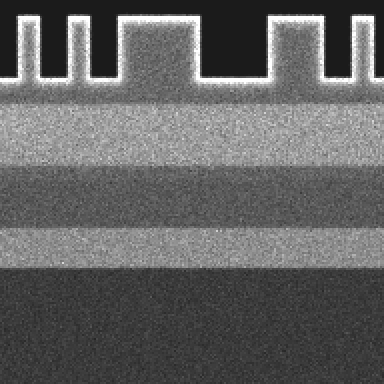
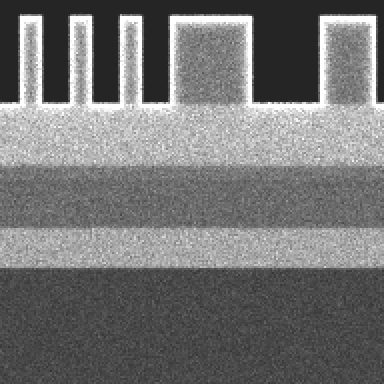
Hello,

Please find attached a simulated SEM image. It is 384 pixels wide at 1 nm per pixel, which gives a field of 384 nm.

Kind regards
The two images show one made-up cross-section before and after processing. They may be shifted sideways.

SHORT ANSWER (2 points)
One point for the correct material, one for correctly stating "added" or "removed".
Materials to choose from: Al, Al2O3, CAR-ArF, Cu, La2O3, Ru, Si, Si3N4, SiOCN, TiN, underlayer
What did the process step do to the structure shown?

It removed underlayer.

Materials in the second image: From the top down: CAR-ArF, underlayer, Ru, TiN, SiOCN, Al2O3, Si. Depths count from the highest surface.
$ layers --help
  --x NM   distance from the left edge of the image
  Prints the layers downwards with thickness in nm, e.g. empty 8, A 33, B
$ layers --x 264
empty 88, Ru 62, TiN 14, SiOCN 48, Al2O3 40, Si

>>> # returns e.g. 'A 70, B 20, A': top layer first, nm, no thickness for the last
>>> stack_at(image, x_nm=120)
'CAR-ArF 62, underlayer 26, Ru 62, TiN 14, SiOCN 48, Al2O3 40, Si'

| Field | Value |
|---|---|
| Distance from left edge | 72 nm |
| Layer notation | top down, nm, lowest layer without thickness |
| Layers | CAR-ArF 62, underlayer 26, Ru 62, TiN 14, SiOCN 48, Al2O3 40, Si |